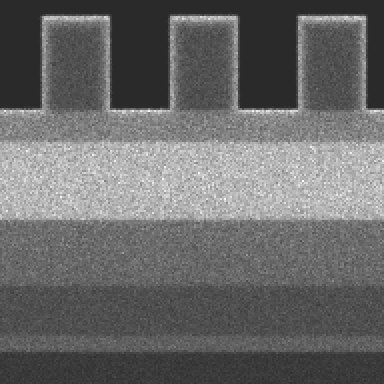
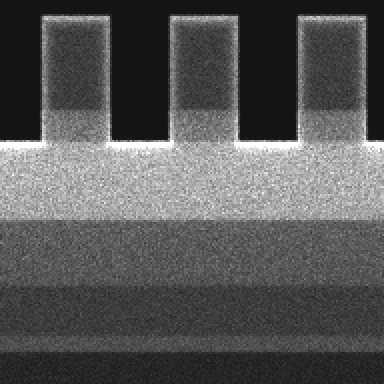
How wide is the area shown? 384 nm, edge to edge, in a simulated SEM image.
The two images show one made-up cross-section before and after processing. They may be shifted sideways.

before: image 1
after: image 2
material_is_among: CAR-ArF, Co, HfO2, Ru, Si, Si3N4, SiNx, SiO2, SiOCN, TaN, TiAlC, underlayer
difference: Ru, removed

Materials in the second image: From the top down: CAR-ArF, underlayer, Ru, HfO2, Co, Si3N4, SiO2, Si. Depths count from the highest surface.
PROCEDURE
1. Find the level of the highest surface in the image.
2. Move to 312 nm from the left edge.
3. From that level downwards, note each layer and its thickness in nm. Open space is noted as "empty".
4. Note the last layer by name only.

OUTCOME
CAR-ArF 60, underlayer 34, Ru 32, HfO2 78, Co 66, Si3N4 50, SiO2 16, Si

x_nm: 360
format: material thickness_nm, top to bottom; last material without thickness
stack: CAR-ArF 60, underlayer 34, Ru 32, HfO2 78, Co 66, Si3N4 50, SiO2 16, Si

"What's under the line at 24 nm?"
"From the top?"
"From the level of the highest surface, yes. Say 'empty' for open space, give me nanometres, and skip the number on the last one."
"empty 126, HfO2 78, Co 66, Si3N4 50, SiO2 16, Si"